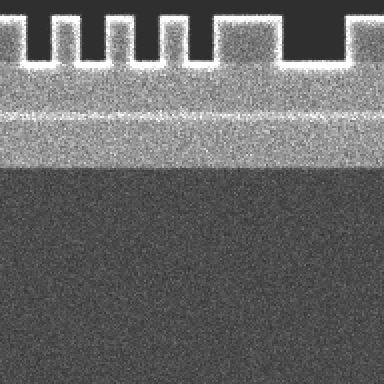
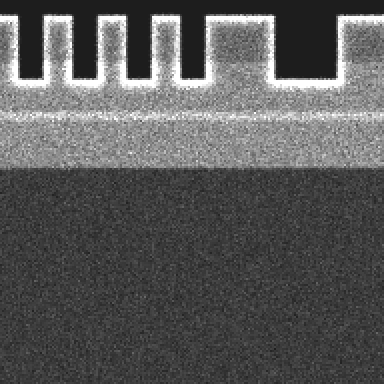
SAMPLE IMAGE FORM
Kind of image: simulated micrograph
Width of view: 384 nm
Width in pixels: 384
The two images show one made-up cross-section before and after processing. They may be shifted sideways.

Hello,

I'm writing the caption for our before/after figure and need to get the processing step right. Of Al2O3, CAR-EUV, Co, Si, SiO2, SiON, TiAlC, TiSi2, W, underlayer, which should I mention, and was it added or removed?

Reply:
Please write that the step removed SiO2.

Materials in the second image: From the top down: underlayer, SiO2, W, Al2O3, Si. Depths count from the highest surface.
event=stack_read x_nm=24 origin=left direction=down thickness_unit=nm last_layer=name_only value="empty 64, SiO2 32, W 8, Al2O3 48, Si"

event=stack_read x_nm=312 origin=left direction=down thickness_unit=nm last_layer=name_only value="empty 64, SiO2 32, W 8, Al2O3 48, Si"